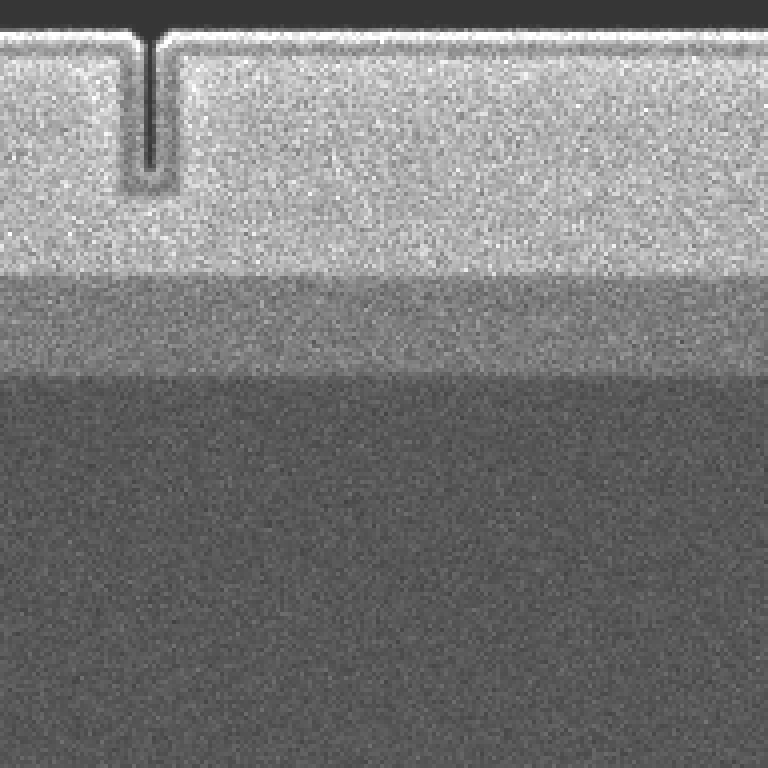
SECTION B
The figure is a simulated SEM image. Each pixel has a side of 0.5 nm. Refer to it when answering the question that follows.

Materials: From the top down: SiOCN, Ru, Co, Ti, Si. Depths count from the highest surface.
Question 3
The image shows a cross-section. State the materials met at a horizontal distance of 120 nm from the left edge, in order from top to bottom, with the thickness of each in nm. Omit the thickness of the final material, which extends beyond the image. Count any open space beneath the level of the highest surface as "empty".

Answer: SiOCN 12, Ru 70, Co 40, Ti 50, Si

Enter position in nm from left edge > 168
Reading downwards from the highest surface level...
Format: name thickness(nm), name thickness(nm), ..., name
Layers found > SiOCN 12, Ru 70, Co 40, Ti 50, Si